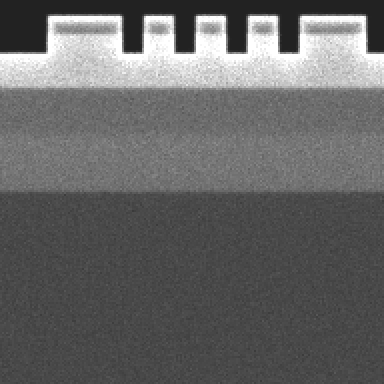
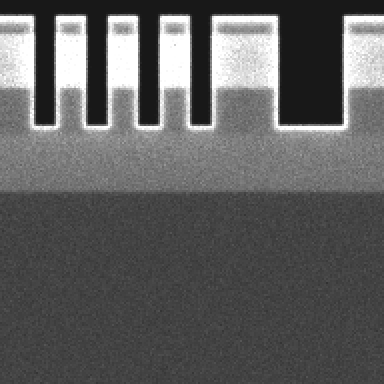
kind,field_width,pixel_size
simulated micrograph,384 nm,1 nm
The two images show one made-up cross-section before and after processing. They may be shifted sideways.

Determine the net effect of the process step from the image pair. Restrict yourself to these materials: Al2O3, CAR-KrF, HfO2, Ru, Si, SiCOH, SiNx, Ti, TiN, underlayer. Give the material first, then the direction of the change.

Ru and SiNx: removed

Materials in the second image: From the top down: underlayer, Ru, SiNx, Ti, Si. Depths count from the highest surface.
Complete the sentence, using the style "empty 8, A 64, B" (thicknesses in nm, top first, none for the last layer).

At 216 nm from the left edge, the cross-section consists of underlayer 18, Ru 54, SiNx 46, Ti 58, Si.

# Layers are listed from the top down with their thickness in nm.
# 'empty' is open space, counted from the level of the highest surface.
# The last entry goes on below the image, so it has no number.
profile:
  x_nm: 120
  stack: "underlayer 18, Ru 54, SiNx 46, Ti 58, Si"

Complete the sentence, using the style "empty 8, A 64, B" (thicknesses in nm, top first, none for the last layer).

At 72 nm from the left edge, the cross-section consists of underlayer 18, Ru 54, SiNx 46, Ti 58, Si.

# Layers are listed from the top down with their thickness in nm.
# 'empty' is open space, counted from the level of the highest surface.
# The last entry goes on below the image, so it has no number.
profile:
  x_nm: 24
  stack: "underlayer 18, Ru 54, SiNx 46, Ti 58, Si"